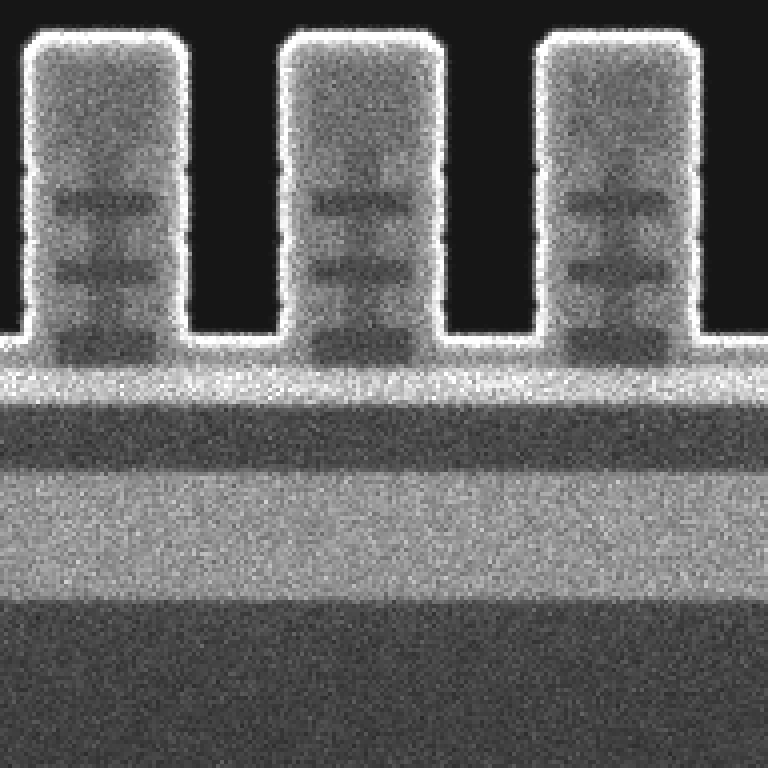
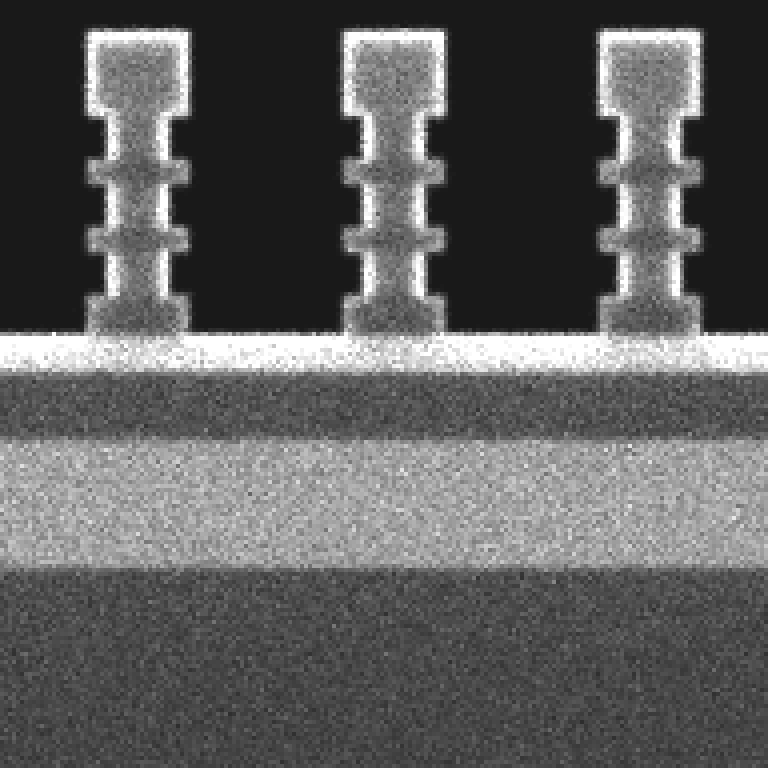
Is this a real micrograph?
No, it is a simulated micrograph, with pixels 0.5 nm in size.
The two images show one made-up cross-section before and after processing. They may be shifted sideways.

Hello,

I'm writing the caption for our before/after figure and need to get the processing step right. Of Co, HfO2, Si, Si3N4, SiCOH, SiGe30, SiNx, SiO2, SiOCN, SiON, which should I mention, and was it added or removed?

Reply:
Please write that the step removed Si3N4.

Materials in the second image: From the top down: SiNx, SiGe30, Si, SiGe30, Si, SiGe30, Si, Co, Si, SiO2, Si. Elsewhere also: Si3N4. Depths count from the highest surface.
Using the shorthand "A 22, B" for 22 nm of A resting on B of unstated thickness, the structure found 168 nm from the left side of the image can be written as empty 152, Co 18, Si 34, SiO2 64, Si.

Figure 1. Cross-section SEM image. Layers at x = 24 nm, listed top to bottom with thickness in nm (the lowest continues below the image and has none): empty 152, Co 18, Si 34, SiO2 64, Si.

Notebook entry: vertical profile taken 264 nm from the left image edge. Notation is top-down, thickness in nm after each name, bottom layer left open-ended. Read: empty 152, Co 18, Si 34, SiO2 64, Si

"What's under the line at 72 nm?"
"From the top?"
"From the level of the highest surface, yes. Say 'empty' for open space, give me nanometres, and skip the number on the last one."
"SiNx 42, SiGe30 22, Si 12, SiGe30 22, Si 12, SiGe30 22, Si 20, Co 18, Si 34, SiO2 64, Si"